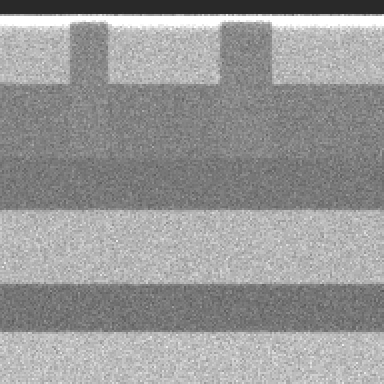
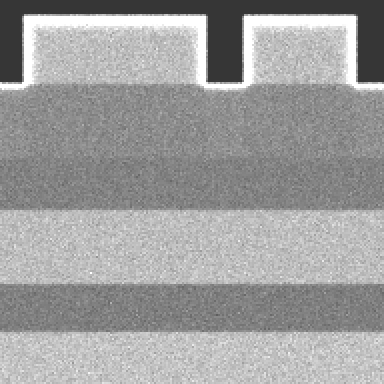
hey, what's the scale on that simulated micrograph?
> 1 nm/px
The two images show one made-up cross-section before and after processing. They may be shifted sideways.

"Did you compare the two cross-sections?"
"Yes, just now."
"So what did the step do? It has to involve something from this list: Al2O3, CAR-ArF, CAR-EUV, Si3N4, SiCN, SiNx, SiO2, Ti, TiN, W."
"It removed Si3N4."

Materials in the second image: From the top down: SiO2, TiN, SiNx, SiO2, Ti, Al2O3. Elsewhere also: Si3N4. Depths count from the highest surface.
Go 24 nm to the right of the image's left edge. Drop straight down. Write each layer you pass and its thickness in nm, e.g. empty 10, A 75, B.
SiO2 68, TiN 74, SiNx 52, SiO2 74, Ti 48, Al2O3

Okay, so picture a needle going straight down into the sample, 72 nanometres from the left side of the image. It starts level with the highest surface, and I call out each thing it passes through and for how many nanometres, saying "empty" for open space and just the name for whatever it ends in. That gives SiO2 68, TiN 74, SiNx 52, SiO2 74, Ti 48, Al2O3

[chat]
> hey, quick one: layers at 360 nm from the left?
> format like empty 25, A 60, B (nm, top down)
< empty 68, Si3N4 74, SiNx 52, SiO2 74, Ti 48, Al2O3